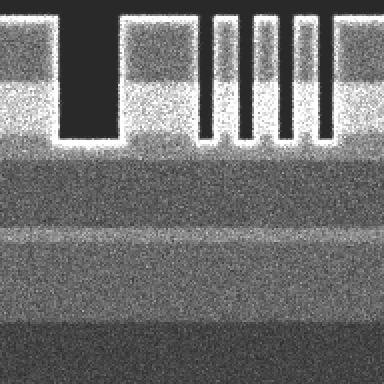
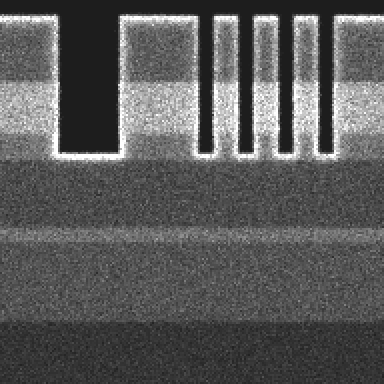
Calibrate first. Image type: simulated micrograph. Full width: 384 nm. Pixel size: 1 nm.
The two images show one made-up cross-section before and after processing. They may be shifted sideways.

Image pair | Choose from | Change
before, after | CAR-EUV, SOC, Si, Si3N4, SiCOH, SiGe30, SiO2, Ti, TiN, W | SiO2 (removed)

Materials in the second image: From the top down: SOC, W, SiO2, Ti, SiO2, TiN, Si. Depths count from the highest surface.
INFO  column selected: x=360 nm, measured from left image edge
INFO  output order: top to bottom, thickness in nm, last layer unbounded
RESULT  SOC 66, W 52, SiO2 26, Ti 68, SiO2 14, TiN 80, Si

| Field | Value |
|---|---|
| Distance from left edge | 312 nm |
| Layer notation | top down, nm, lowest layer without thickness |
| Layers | SOC 66, W 52, SiO2 26, Ti 68, SiO2 14, TiN 80, Si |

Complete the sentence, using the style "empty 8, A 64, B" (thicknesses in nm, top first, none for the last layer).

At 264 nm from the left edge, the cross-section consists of SOC 66, W 52, SiO2 26, Ti 68, SiO2 14, TiN 80, Si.